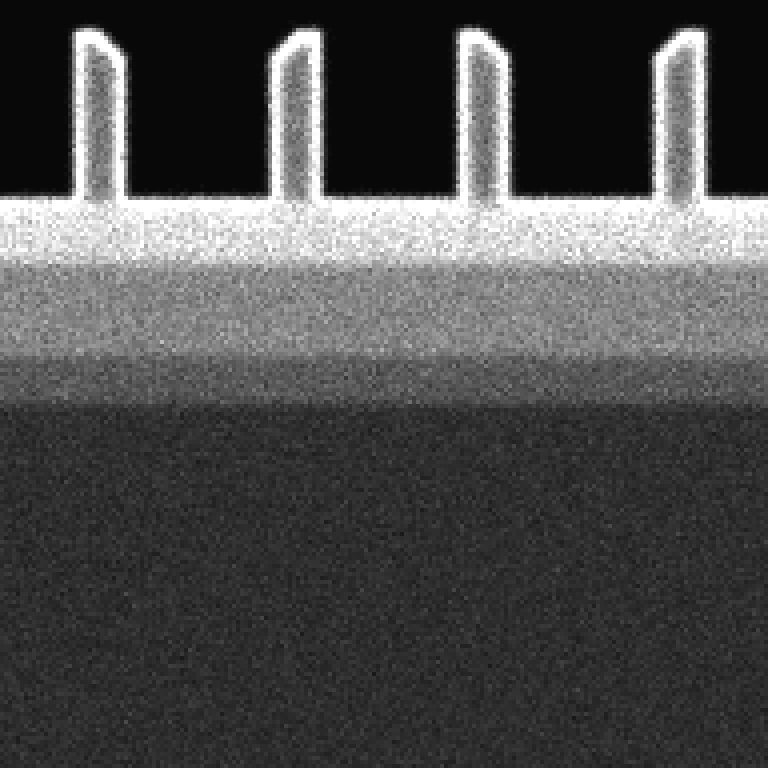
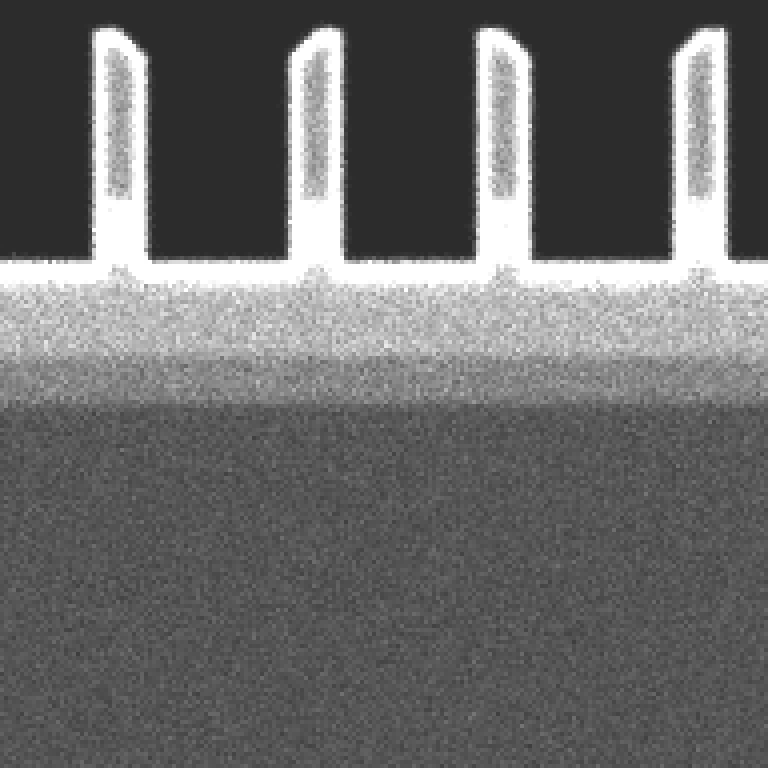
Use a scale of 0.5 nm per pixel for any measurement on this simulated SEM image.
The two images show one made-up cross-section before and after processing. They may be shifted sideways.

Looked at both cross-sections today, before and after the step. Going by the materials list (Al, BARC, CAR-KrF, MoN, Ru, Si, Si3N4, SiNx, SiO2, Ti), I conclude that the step removed Ru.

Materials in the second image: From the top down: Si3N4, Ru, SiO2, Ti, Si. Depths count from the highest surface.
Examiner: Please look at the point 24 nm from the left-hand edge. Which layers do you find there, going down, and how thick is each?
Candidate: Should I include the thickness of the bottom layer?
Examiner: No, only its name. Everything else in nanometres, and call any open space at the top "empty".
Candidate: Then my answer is empty 116, SiO2 46, Ti 24, Si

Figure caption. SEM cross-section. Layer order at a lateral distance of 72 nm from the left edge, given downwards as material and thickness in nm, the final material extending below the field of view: empty 116, SiO2 46, Ti 24, Si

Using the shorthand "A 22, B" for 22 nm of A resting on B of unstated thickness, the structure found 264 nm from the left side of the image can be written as empty 116, SiO2 46, Ti 24, Si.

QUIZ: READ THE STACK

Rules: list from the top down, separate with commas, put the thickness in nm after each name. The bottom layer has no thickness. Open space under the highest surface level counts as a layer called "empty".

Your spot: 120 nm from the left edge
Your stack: empty 116, SiO2 46, Ti 24, Si